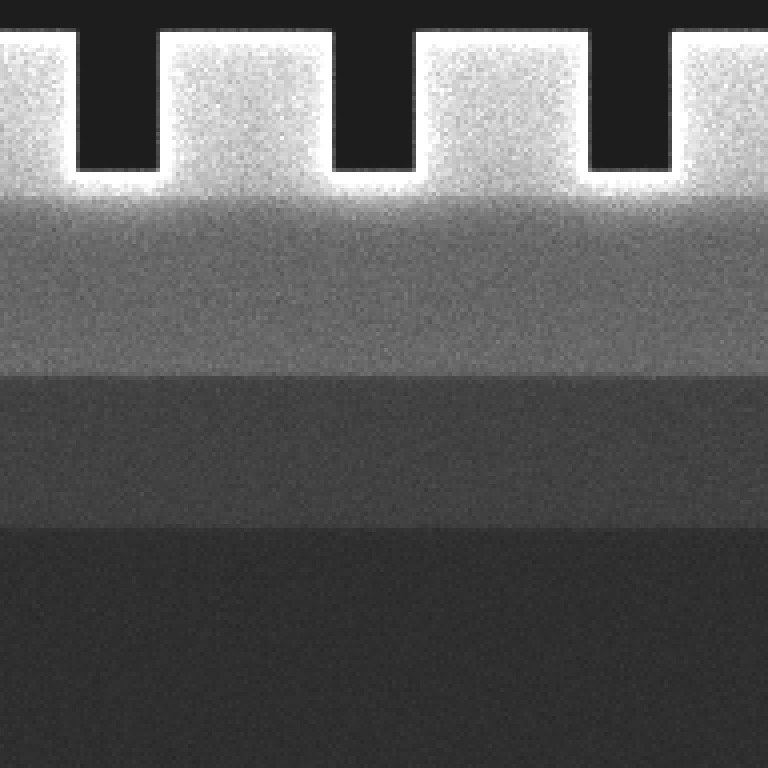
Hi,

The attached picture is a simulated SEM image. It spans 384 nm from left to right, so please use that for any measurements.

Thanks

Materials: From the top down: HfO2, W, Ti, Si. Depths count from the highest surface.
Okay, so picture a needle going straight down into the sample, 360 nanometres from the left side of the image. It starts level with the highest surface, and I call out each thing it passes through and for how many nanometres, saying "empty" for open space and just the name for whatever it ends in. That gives HfO2 82, W 90, Ti 76, Si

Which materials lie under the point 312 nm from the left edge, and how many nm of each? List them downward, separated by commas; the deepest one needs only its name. empty 70, HfO2 12, W 90, Ti 76, Si